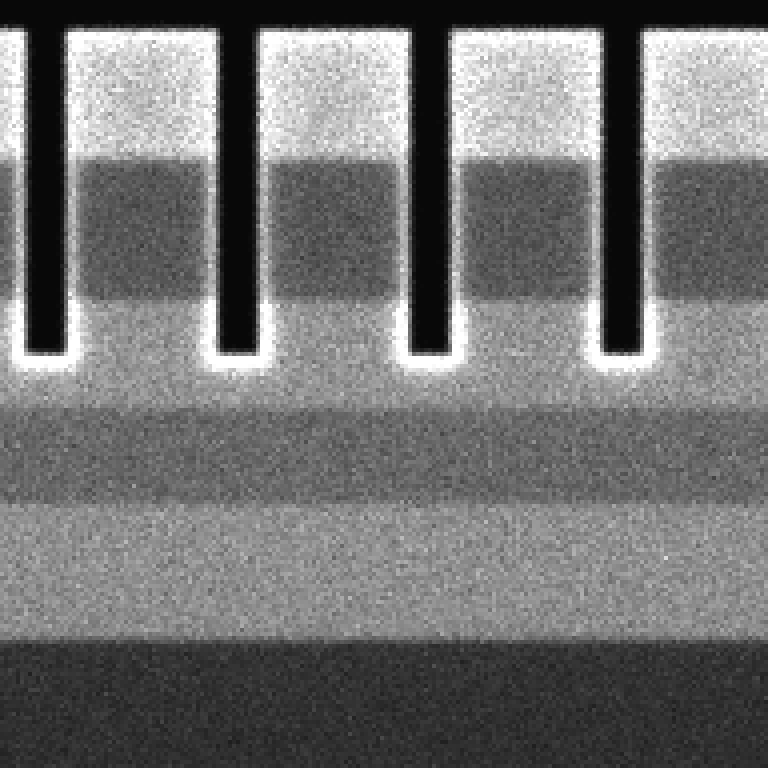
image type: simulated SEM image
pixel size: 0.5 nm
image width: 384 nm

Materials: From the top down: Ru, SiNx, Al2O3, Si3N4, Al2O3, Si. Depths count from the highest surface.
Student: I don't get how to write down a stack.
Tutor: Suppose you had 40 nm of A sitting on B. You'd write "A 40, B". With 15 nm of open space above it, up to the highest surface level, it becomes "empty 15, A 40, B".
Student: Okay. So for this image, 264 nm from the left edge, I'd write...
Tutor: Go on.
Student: Ru 64, SiNx 70, Al2O3 54, Si3N4 48, Al2O3 68, Si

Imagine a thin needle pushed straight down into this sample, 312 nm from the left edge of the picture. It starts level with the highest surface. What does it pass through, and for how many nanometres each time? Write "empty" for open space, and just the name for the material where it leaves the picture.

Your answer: empty 162, Al2O3 26, Si3N4 48, Al2O3 68, Si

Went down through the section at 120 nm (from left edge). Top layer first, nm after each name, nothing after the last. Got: empty 162, Al2O3 26, Si3N4 48, Al2O3 68, Si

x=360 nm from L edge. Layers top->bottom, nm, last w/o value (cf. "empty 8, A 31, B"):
Ru 64, SiNx 70, Al2O3 54, Si3N4 48, Al2O3 68, Si